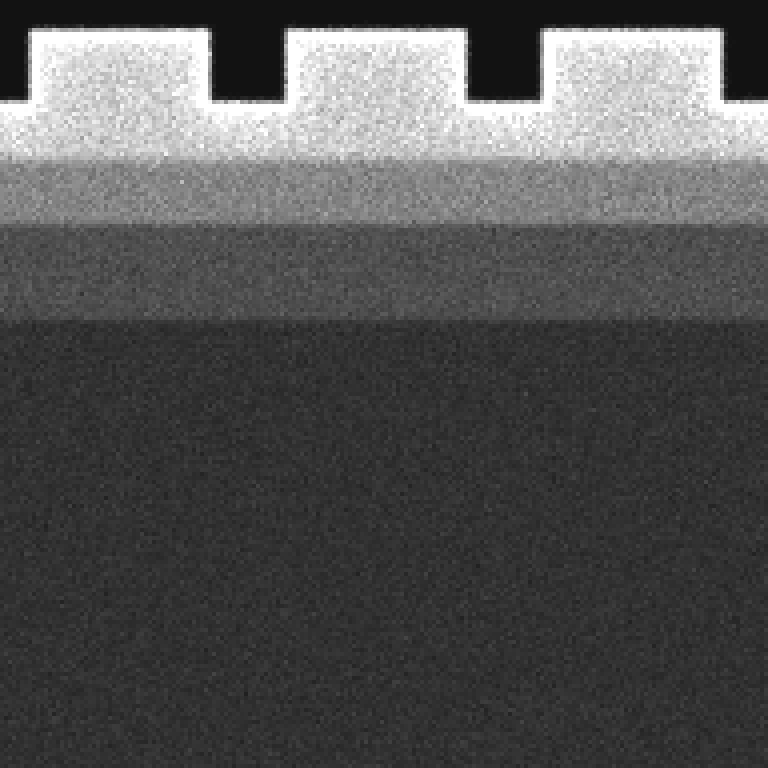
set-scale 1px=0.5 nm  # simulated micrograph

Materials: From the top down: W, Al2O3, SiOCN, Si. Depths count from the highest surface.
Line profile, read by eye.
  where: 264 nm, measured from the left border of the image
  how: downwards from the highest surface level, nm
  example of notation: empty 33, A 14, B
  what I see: empty 36, W 28, Al2O3 32, SiOCN 48, Si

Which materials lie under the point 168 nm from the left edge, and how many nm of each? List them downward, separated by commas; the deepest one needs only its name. W 64, Al2O3 32, SiOCN 48, Si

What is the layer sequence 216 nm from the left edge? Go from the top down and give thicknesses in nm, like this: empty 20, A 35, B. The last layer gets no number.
W 64, Al2O3 32, SiOCN 48, Si